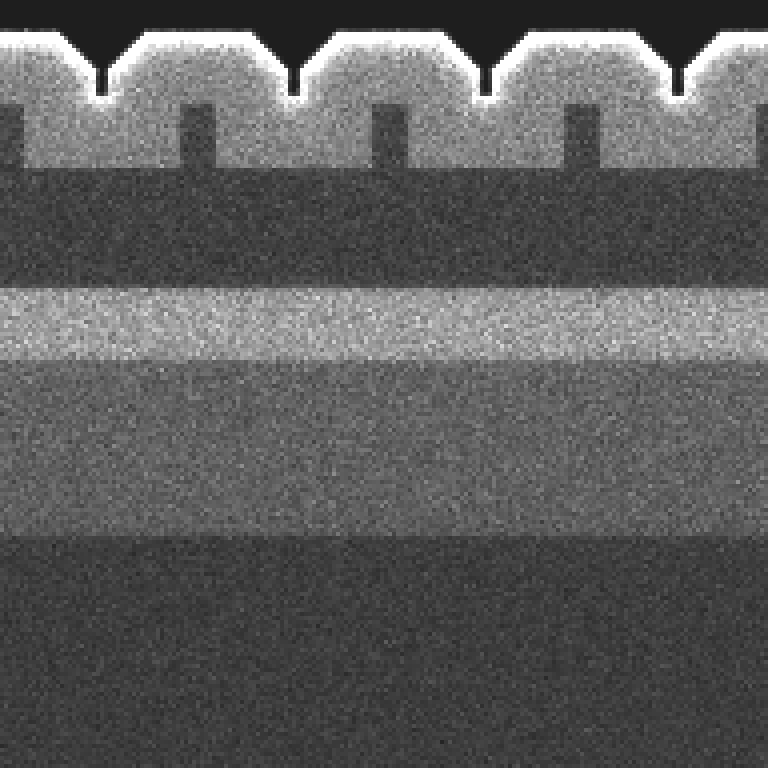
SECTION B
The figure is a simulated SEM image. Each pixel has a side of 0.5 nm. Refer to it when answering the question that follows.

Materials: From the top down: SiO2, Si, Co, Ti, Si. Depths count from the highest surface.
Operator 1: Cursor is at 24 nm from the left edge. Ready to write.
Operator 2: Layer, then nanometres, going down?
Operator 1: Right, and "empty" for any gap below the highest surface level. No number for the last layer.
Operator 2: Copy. SiO2 68, Si 60, Co 36, Ti 88, Si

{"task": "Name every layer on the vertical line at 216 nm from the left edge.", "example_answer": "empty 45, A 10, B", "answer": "SiO2 68, Si 60, Co 36, Ti 88, Si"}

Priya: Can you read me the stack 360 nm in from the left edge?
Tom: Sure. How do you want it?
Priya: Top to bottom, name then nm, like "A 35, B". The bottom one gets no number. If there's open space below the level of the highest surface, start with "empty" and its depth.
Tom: SiO2 68, Si 60, Co 36, Ti 88, Si